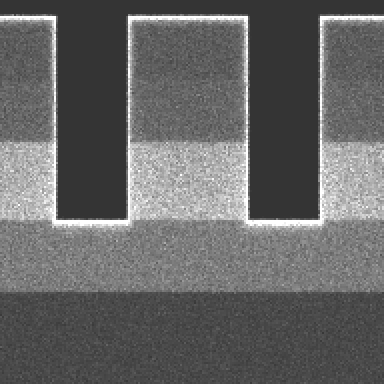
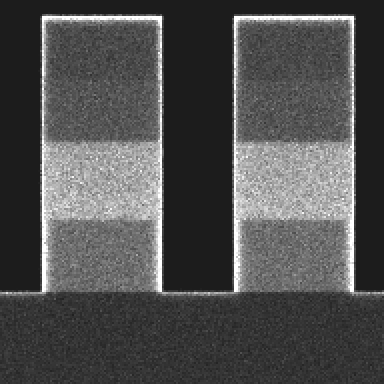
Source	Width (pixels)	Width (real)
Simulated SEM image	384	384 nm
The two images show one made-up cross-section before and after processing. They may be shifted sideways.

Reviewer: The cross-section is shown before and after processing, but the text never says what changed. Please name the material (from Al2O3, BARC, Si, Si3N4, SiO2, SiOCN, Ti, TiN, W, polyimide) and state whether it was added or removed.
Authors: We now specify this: SiO2, removed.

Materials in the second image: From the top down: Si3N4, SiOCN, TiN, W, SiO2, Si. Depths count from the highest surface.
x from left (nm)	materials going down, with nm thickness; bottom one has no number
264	Si3N4 10, SiOCN 54, TiN 62, W 78, SiO2 72, Si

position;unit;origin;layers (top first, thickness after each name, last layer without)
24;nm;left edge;empty 276, Si